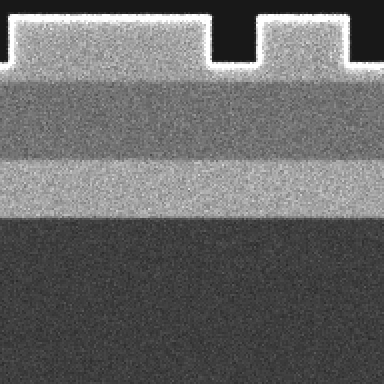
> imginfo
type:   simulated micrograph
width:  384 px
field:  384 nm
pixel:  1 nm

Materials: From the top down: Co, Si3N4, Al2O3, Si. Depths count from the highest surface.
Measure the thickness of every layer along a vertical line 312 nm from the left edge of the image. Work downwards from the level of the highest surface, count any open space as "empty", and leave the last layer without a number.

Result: Co 66, Si3N4 78, Al2O3 58, Si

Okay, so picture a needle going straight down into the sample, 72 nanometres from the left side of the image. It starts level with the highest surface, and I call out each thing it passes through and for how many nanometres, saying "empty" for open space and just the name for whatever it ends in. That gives Co 66, Si3N4 78, Al2O3 58, Si